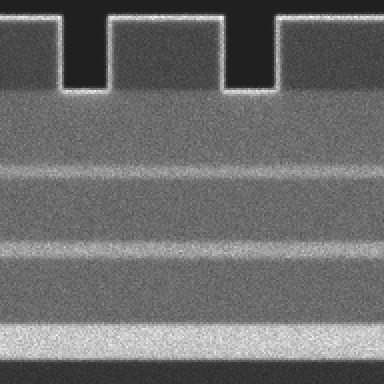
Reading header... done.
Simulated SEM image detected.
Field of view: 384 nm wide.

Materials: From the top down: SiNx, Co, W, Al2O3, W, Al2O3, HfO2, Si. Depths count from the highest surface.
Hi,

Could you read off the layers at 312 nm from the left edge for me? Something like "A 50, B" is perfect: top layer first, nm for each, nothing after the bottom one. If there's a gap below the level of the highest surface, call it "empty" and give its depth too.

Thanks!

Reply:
SiNx 74, Co 76, W 12, Al2O3 64, W 16, Al2O3 66, HfO2 36, Si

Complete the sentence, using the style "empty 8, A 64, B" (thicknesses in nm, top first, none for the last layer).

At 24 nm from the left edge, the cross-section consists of SiNx 74, Co 76, W 12, Al2O3 64, W 16, Al2O3 66, HfO2 36, Si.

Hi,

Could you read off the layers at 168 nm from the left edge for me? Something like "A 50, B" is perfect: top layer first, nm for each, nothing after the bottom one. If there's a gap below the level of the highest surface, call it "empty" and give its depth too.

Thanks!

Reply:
SiNx 74, Co 76, W 12, Al2O3 64, W 16, Al2O3 66, HfO2 36, Si